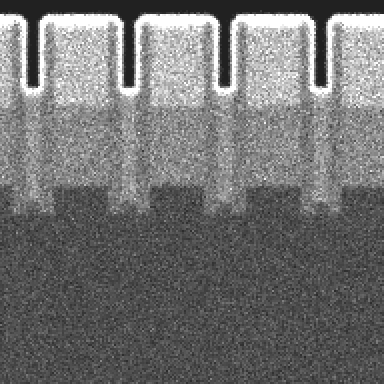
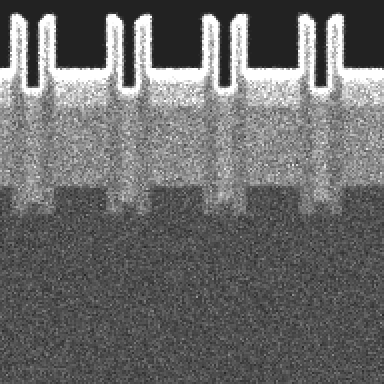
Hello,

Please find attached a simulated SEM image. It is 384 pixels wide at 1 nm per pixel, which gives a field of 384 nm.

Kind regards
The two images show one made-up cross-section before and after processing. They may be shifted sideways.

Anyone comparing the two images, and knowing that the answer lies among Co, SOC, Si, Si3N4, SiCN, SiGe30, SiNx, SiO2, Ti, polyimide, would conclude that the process removed SiO2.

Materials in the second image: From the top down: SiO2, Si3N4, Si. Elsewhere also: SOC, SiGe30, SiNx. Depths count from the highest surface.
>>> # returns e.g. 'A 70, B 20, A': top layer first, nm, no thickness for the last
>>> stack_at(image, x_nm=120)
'empty 6, SiNx 192, Si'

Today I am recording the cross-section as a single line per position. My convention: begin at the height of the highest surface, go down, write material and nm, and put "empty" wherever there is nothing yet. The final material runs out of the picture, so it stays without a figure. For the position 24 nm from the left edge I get empty 6, SiNx 192, Si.